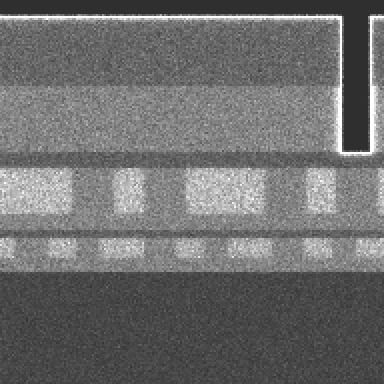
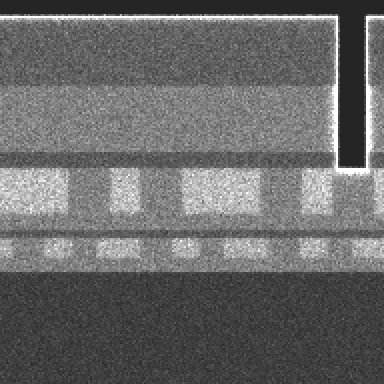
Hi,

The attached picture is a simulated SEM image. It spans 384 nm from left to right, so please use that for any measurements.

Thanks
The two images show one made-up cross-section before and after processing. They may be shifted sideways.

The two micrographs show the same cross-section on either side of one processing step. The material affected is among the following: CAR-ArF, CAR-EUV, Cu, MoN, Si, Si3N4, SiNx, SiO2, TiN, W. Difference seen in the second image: SiNx removed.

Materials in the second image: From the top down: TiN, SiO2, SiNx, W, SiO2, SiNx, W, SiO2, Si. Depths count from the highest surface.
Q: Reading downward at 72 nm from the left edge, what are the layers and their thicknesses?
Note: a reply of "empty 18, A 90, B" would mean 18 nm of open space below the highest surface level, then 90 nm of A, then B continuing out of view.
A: TiN 70, SiO2 66, SiNx 16, SiO2 62, SiNx 8, SiO2 34, Si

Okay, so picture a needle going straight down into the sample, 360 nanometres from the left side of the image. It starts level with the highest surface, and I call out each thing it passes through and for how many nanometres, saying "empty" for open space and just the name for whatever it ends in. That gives empty 152, SiO2 62, SiNx 8, W 20, SiO2 14, Si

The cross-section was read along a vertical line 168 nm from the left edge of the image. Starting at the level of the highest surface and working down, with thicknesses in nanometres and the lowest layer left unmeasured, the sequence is TiN 70, SiO2 66, SiNx 16, SiO2 62, SiNx 8, SiO2 34, Si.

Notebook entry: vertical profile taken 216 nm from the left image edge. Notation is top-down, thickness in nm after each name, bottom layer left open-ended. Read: TiN 70, SiO2 66, SiNx 16, W 46, SiO2 16, SiNx 8, SiO2 34, Si